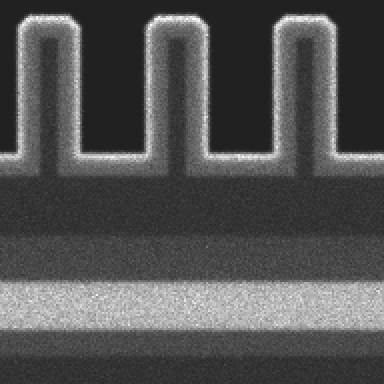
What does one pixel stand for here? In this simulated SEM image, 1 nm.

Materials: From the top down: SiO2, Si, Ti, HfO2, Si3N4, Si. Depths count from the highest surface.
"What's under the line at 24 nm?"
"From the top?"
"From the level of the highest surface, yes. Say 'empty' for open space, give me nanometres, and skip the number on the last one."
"empty 4, SiO2 156, Si 60, Ti 46, HfO2 48, Si3N4 26, Si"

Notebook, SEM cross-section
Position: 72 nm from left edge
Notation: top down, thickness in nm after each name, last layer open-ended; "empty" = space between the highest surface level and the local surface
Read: empty 4, SiO2 156, Si 60, Ti 46, HfO2 48, Si3N4 26, Si